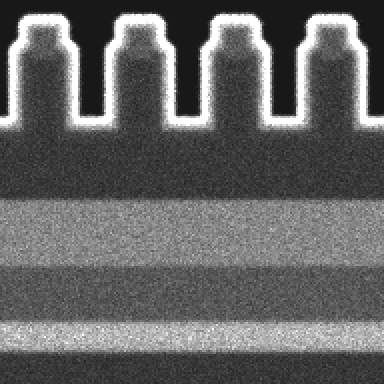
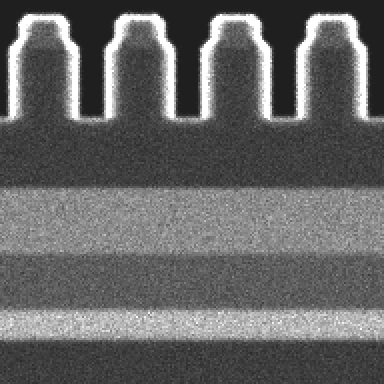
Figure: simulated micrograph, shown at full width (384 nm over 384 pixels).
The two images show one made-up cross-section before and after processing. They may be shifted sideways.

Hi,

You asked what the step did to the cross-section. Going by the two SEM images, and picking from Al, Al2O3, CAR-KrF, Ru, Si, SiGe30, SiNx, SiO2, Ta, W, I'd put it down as Al2O3, removed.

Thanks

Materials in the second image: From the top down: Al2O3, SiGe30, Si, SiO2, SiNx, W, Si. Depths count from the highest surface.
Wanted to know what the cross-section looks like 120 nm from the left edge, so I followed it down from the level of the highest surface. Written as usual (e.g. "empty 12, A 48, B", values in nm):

empty 2, Al2O3 22, SiGe30 88, Si 60, SiO2 66, SiNx 56, W 30, Si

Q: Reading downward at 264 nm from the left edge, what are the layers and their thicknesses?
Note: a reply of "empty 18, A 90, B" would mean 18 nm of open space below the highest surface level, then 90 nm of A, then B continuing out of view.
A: empty 28, Al2O3 74, SiGe30 10, Si 60, SiO2 66, SiNx 56, W 30, Si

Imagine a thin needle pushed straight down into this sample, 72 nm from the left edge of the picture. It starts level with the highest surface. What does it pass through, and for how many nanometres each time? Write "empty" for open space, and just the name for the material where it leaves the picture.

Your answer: empty 28, Al2O3 74, SiGe30 10, Si 60, SiO2 66, SiNx 56, W 30, Si